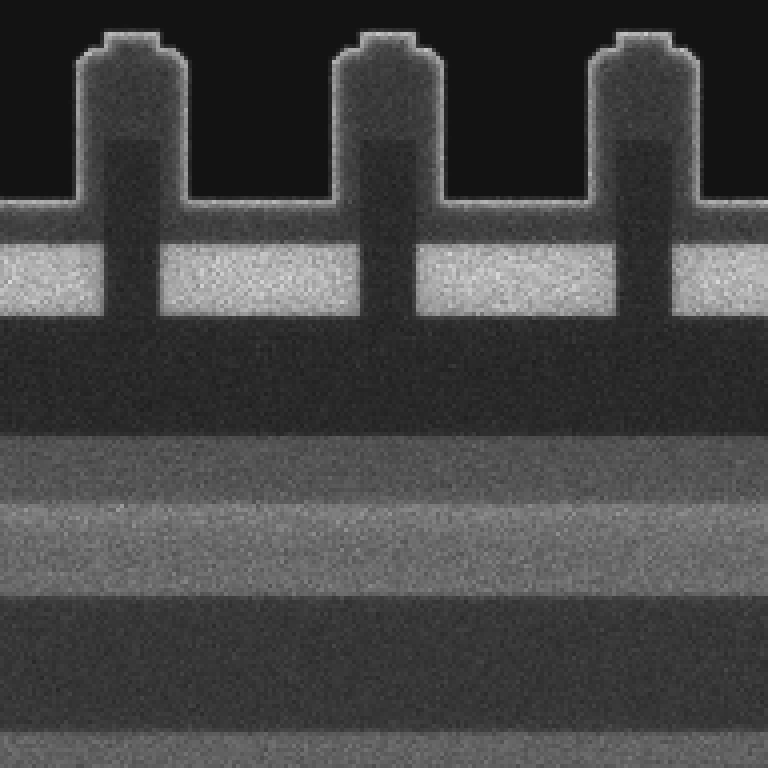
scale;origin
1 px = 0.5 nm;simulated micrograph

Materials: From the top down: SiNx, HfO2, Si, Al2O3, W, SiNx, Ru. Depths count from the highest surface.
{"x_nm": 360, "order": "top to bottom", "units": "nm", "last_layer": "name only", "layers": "empty 84, SiNx 22, HfO2 36, Si 60, Al2O3 34, W 46, SiNx 68, Ru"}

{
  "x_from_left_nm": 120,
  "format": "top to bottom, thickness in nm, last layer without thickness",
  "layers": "empty 84, SiNx 22, HfO2 36, Si 60, Al2O3 34, W 46, SiNx 68, Ru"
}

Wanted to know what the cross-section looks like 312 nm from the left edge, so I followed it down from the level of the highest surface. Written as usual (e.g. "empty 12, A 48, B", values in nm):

SiNx 54, Si 148, Al2O3 34, W 46, SiNx 68, Ru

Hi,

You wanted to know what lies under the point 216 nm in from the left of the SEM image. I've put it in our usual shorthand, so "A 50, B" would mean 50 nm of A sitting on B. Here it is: empty 10, SiNx 96, HfO2 36, Si 60, Al2O3 34, W 46, SiNx 68, Ru